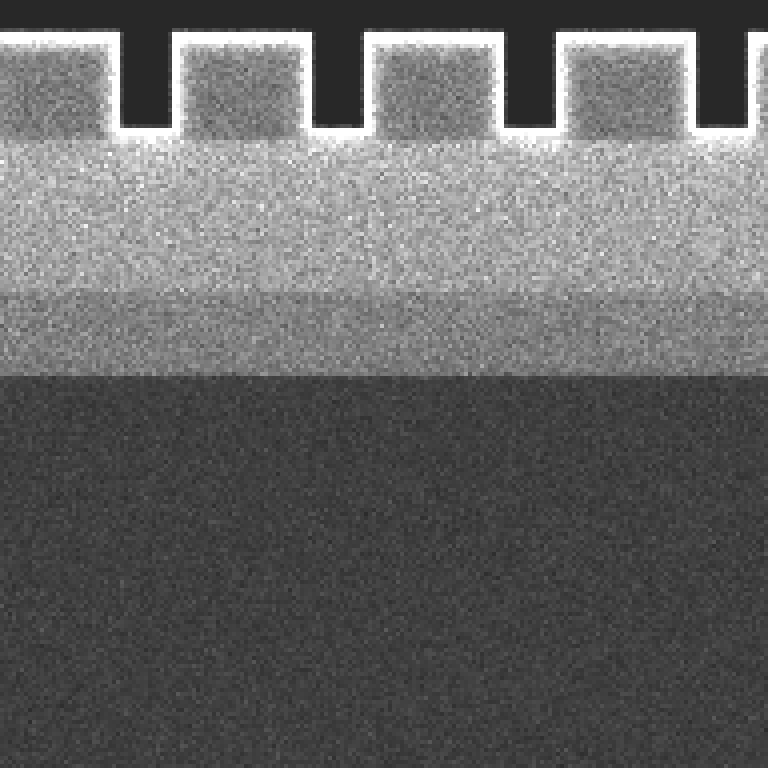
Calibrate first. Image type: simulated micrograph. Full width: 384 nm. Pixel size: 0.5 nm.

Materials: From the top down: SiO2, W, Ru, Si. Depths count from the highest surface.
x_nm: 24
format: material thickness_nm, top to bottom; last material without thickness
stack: SiO2 54, W 76, Ru 42, Si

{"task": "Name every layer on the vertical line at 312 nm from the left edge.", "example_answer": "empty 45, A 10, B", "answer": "SiO2 54, W 76, Ru 42, Si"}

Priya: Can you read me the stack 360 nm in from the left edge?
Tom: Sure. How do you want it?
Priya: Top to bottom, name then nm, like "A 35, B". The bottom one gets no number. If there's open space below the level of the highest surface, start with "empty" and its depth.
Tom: empty 48, SiO2 6, W 76, Ru 42, Si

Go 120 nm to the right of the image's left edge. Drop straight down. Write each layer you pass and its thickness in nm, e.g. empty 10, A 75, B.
SiO2 54, W 76, Ru 42, Si